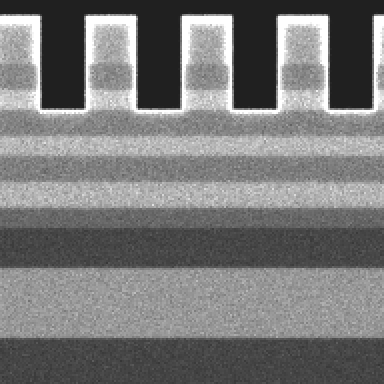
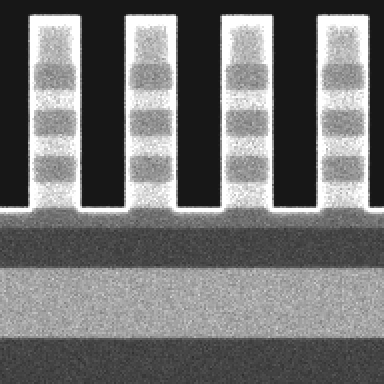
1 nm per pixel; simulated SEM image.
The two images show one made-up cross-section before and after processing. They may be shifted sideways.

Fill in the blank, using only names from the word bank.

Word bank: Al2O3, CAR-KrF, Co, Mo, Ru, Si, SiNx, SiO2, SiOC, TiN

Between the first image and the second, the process removed Co and TiN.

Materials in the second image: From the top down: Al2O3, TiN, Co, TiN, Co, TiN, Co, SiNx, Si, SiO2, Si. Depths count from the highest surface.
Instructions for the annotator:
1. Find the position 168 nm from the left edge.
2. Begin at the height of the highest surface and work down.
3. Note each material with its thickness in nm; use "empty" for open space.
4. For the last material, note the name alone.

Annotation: Al2O3 48, TiN 26, Co 20, TiN 26, Co 20, TiN 26, Co 26, SiNx 20, Si 40, SiO2 70, Si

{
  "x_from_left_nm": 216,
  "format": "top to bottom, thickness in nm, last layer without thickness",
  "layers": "empty 192, SiNx 20, Si 40, SiO2 70, Si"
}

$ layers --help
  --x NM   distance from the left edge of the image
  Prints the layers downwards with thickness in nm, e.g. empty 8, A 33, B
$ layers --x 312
empty 192, SiNx 20, Si 40, SiO2 70, Si